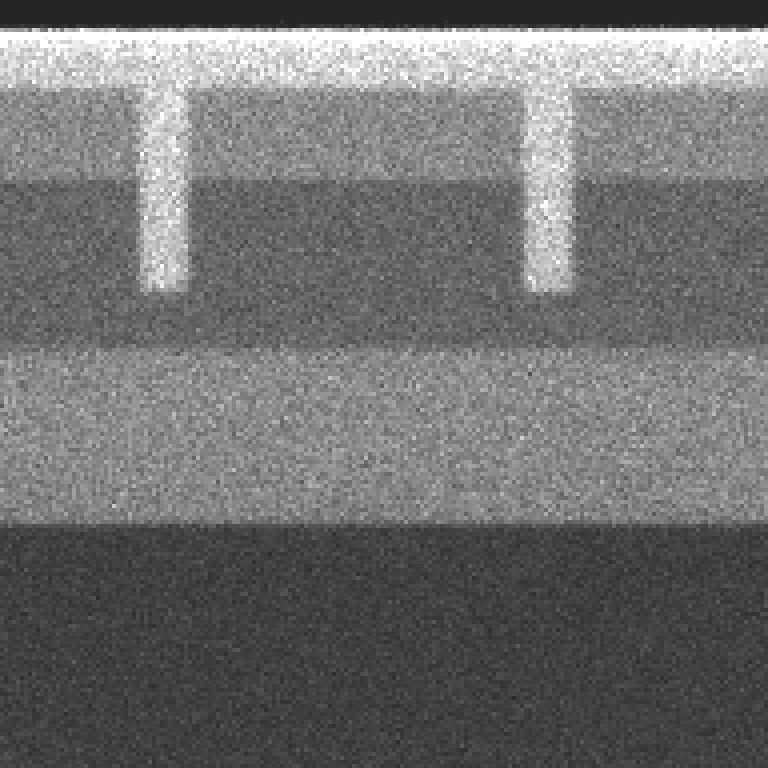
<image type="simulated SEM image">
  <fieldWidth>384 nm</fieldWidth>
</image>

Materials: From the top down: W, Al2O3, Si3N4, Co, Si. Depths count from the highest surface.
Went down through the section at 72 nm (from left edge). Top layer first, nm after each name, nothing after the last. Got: W 130, Si3N4 28, Co 88, Si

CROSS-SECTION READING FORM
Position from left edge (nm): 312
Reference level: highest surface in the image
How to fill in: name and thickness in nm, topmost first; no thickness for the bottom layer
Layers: W 28, Al2O3 46, Si3N4 84, Co 88, Si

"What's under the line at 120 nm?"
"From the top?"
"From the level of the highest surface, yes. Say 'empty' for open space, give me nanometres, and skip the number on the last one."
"W 28, Al2O3 46, Si3N4 84, Co 88, Si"